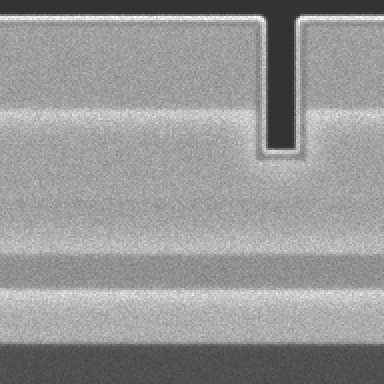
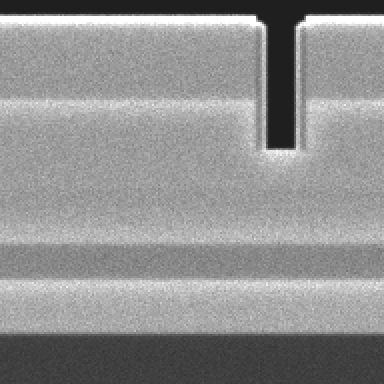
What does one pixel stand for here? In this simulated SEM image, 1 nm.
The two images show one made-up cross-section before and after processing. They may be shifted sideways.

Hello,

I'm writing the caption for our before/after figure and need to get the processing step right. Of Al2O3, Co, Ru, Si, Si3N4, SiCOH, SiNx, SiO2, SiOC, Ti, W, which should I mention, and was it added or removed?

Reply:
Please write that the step removed SiNx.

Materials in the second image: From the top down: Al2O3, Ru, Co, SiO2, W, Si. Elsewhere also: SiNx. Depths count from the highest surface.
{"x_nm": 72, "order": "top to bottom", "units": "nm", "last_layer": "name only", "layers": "Al2O3 84, Ru 88, Co 56, SiO2 36, W 54, Si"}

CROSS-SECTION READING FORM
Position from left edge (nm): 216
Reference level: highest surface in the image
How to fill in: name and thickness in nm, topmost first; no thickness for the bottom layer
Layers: Al2O3 84, Ru 88, Co 56, SiO2 36, W 54, Si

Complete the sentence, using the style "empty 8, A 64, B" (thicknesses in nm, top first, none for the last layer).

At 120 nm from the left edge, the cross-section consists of Al2O3 84, Ru 88, Co 56, SiO2 36, W 54, Si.